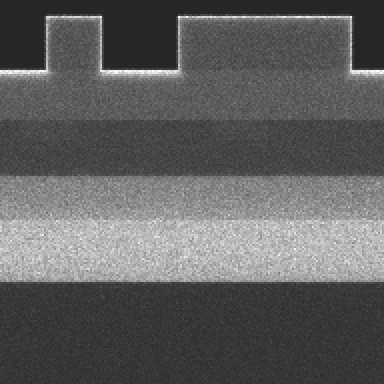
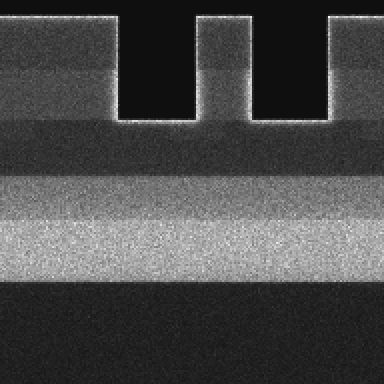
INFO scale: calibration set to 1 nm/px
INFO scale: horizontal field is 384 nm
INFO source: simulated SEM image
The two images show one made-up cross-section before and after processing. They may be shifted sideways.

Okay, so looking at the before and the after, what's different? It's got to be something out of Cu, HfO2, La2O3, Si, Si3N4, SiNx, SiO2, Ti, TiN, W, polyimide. SiO2, removed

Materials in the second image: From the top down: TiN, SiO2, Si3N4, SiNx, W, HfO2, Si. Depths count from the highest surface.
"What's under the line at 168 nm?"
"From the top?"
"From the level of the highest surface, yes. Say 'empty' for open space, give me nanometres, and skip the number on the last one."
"empty 104, SiNx 56, W 44, HfO2 62, Si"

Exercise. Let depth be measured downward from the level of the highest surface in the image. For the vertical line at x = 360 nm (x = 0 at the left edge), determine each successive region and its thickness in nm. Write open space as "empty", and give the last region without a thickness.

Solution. TiN 54, SiO2 50, SiNx 56, W 44, HfO2 62, Si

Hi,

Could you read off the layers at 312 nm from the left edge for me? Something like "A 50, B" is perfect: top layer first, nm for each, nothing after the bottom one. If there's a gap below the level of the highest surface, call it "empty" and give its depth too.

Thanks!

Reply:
empty 104, SiNx 56, W 44, HfO2 62, Si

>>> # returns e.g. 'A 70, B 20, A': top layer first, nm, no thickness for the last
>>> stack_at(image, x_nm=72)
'TiN 54, SiO2 50, SiNx 56, W 44, HfO2 62, Si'